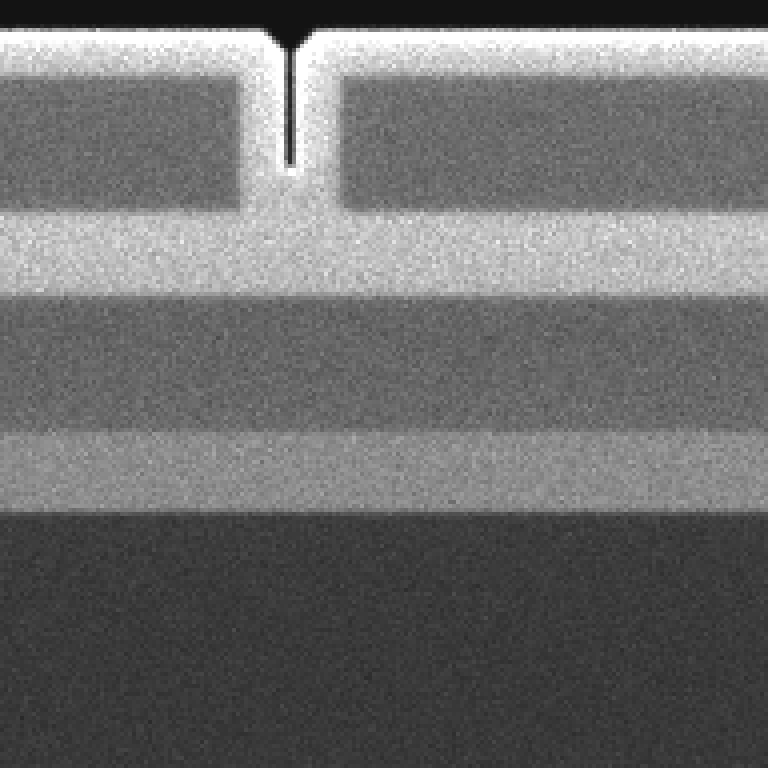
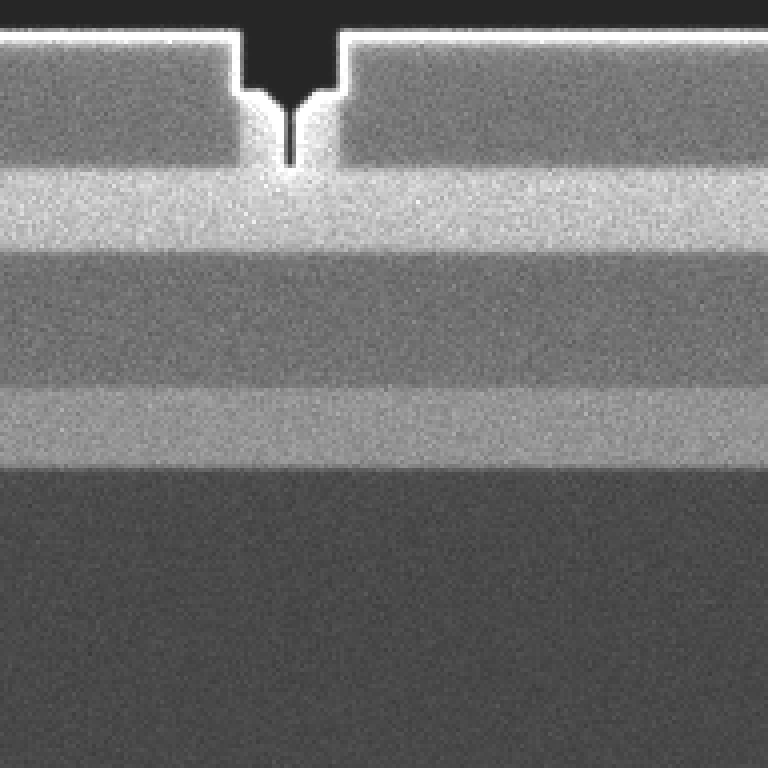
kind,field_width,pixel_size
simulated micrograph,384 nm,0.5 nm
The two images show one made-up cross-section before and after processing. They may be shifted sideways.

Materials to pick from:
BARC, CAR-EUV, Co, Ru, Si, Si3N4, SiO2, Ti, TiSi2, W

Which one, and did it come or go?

Co - removed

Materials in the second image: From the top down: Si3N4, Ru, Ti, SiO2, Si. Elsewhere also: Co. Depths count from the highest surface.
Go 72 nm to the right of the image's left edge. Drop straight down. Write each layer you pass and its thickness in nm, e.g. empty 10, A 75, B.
Si3N4 68, Ru 42, Ti 68, SiO2 40, Si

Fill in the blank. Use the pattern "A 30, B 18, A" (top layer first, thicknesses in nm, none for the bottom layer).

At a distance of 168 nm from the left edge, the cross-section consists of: empty 30, Co 38, Ru 42, Ti 68, SiO2 40, Si